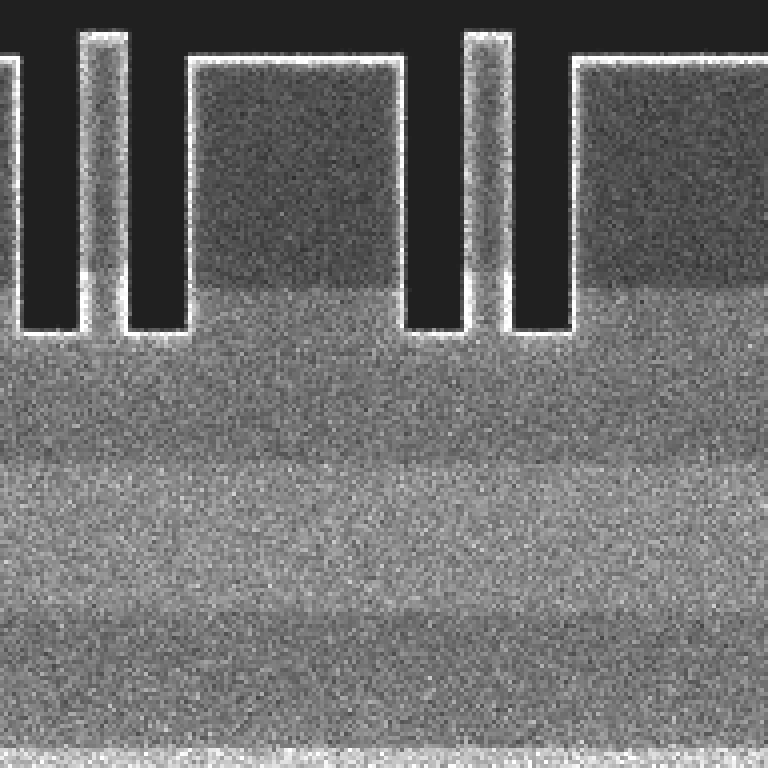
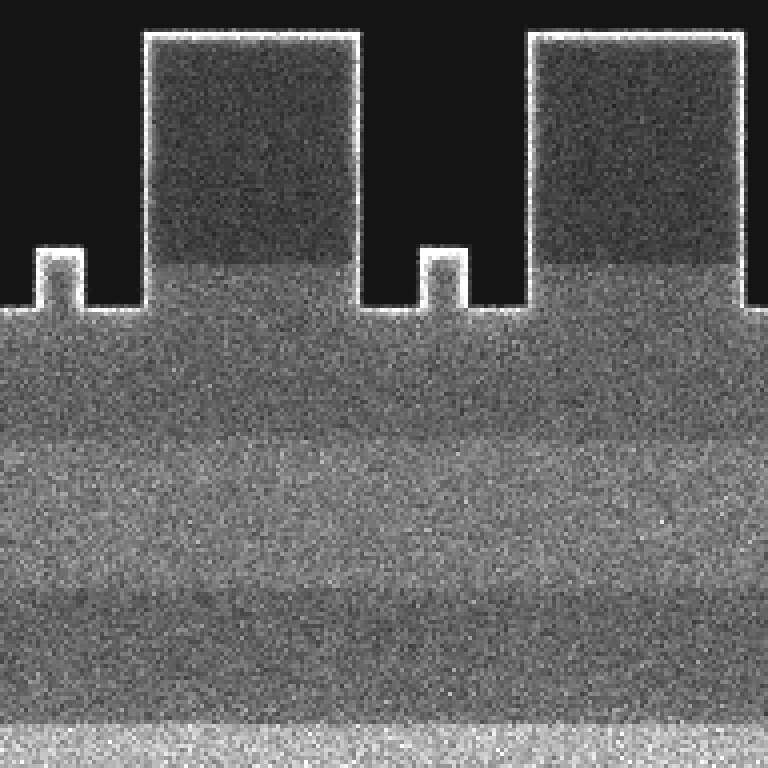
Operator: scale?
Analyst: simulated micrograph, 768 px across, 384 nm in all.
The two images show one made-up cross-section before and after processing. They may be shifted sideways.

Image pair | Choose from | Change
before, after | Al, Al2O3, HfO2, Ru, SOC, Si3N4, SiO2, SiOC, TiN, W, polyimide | SOC (removed)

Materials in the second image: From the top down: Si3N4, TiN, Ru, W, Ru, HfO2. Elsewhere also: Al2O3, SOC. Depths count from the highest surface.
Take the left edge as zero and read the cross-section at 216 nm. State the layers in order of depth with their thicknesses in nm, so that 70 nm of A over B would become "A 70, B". empty 108, Al2O3 30, Ru 66, W 74, Ru 68, HfO2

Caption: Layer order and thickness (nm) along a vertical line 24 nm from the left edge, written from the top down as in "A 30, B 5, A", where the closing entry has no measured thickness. empty 108, Al2O3 30, Ru 66, W 74, Ru 68, HfO2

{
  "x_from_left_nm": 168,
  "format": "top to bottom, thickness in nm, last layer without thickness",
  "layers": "Si3N4 68, TiN 48, Ru 88, W 74, Ru 68, HfO2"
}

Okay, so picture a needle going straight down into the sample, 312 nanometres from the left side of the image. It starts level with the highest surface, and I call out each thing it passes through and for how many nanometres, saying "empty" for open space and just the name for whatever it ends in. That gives Si3N4 68, TiN 48, Ru 88, W 74, Ru 68, HfO2